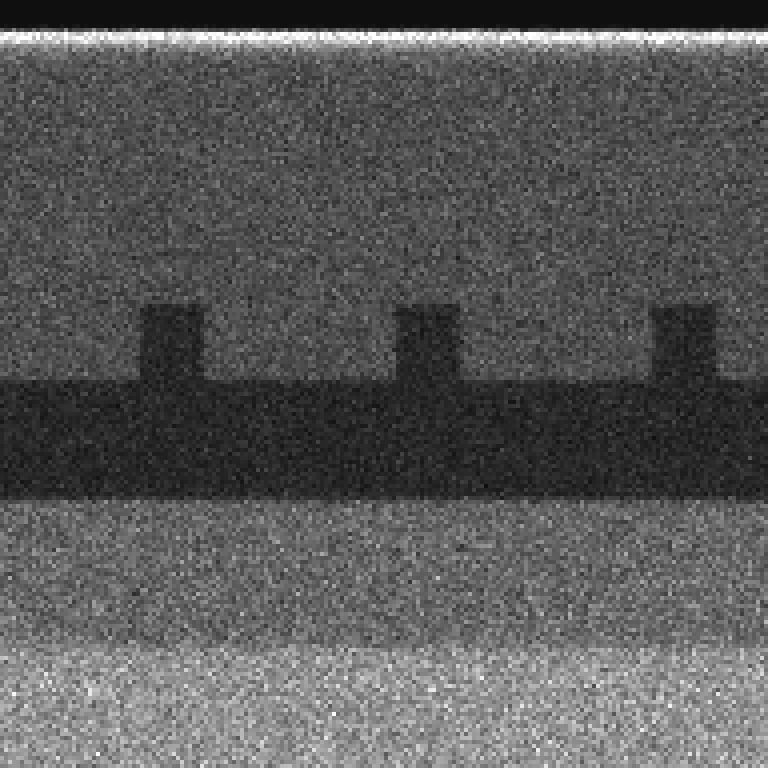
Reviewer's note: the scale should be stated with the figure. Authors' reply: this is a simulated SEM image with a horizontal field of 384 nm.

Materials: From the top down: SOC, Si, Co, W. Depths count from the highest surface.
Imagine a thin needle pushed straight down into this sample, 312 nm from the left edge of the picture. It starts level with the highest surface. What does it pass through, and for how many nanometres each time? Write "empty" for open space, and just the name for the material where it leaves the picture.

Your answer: SOC 174, Si 60, Co 74, W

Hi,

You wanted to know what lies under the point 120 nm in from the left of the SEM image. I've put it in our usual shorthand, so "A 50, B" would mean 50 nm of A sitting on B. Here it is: SOC 174, Si 60, Co 74, W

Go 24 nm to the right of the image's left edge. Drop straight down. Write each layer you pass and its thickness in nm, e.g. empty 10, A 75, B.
SOC 174, Si 60, Co 74, W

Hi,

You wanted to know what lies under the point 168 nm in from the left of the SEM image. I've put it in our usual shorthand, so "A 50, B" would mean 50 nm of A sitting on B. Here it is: SOC 174, Si 60, Co 74, W